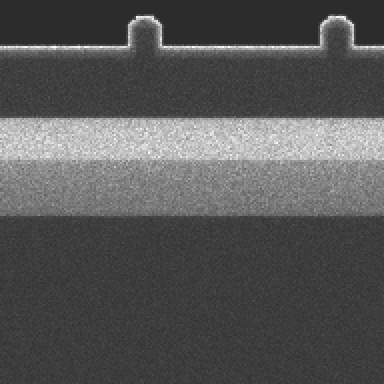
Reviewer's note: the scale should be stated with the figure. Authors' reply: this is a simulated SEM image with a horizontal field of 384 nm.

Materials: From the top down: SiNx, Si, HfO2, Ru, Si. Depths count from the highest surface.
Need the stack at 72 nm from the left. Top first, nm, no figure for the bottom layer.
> empty 30, SiNx 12, Si 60, HfO2 42, Ru 56, Si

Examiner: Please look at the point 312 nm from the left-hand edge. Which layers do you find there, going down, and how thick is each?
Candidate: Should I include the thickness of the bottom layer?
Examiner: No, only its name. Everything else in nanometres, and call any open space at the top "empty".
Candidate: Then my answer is empty 30, SiNx 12, Si 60, HfO2 42, Ru 56, Si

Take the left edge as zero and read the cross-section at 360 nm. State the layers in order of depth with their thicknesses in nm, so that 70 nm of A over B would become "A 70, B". empty 30, SiNx 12, Si 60, HfO2 42, Ru 56, Si